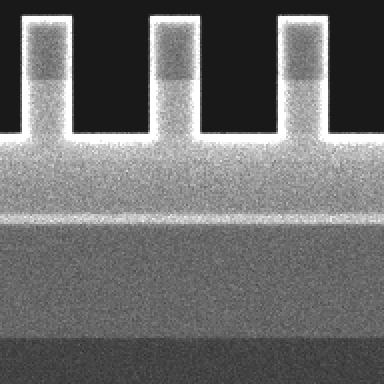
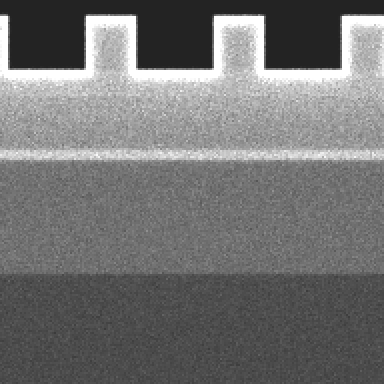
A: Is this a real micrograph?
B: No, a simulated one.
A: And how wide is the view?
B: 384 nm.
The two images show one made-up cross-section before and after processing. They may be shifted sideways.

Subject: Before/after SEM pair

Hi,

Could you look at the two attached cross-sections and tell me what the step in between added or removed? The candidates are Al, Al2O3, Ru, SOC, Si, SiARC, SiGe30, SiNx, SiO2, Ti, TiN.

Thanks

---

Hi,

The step removed SOC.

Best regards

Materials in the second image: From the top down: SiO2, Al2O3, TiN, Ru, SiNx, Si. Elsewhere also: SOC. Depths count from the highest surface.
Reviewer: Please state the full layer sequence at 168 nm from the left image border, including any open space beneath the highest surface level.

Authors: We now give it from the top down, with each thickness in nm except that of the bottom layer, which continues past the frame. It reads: empty 54, Al2O3 26, TiN 54, Ru 10, SiNx 114, Si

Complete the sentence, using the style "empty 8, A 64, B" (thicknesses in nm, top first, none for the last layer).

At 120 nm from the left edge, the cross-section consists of SiO2 54, Al2O3 26, TiN 54, Ru 10, SiNx 114, Si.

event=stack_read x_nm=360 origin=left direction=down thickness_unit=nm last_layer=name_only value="SiO2 54, Al2O3 26, TiN 54, Ru 10, SiNx 114, Si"